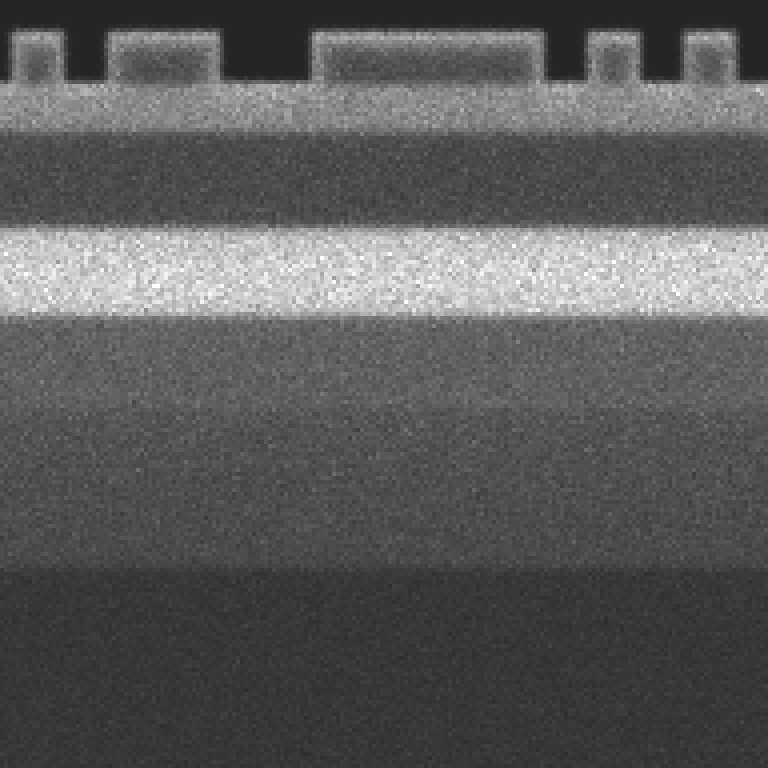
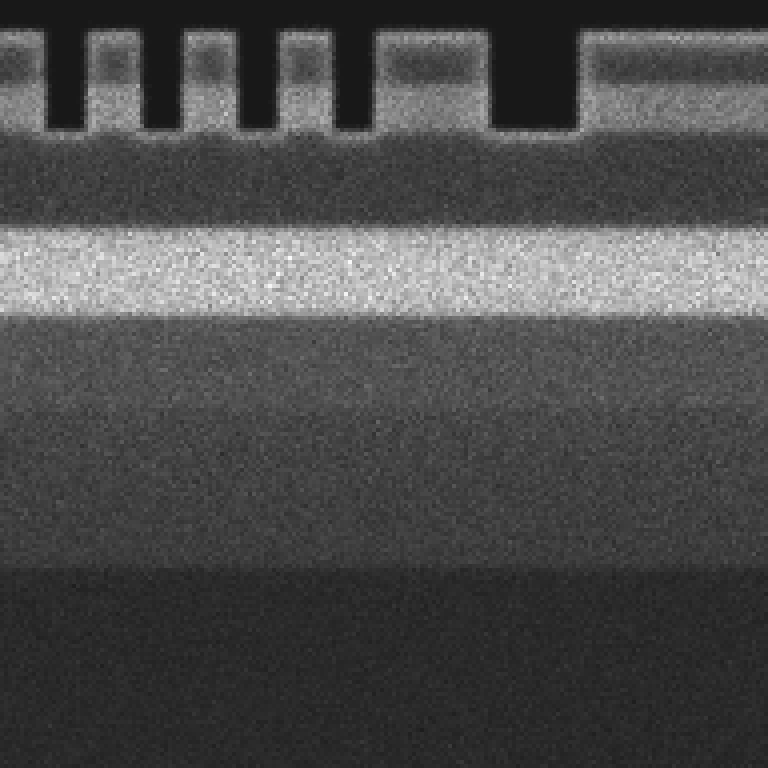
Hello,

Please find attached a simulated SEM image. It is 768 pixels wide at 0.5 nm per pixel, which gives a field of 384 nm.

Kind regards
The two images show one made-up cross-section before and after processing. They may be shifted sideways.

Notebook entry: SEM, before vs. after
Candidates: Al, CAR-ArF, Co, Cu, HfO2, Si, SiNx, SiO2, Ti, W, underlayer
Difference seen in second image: W removed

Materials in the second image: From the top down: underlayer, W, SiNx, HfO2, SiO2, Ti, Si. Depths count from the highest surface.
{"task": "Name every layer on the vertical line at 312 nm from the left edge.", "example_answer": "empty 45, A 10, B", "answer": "underlayer 26, W 24, SiNx 48, HfO2 44, SiO2 46, Ti 80, Si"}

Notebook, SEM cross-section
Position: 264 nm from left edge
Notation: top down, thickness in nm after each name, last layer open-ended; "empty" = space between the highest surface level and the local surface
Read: empty 50, SiNx 48, HfO2 44, SiO2 46, Ti 80, Si